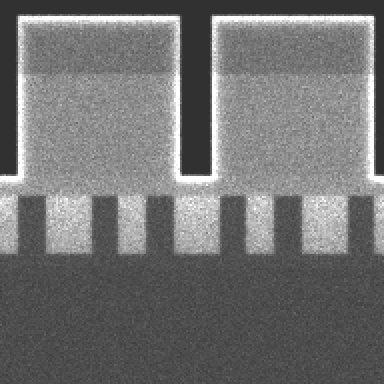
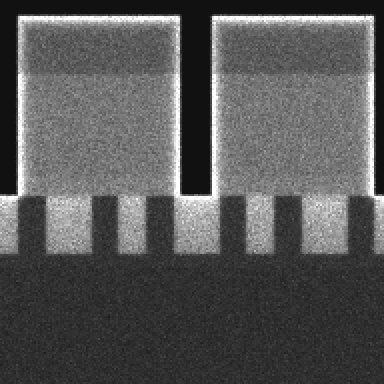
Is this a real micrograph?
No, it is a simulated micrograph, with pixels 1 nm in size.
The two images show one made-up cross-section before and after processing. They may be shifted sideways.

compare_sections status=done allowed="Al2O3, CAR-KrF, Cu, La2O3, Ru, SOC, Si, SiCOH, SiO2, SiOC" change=removed material="Al2O3"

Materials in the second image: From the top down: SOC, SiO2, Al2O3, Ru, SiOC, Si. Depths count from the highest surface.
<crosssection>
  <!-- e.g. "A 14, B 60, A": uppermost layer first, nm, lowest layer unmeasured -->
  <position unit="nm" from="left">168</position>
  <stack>SOC 58, SiO2 102, Al2O3 20, SiOC 72, Si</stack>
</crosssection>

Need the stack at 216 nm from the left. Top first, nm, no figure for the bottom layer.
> SOC 58, SiO2 102, Al2O3 20, Ru 58, SiOC 14, Si